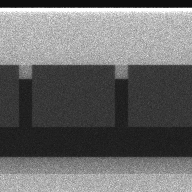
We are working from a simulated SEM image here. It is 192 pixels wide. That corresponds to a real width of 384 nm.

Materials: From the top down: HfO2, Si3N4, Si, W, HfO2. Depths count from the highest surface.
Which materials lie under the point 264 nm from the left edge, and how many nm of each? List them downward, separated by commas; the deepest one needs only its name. HfO2 114, Si3N4 124, Si 60, W 34, HfO2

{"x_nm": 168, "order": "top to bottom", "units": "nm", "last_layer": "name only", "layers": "HfO2 114, Si3N4 124, Si 60, W 34, HfO2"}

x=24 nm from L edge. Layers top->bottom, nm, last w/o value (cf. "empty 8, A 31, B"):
HfO2 114, Si3N4 124, Si 60, W 34, HfO2